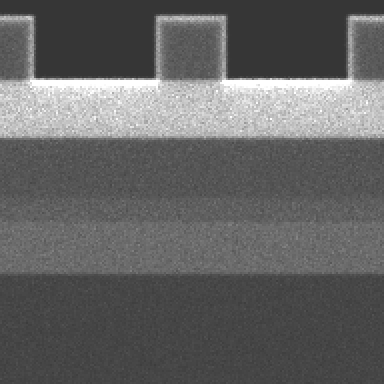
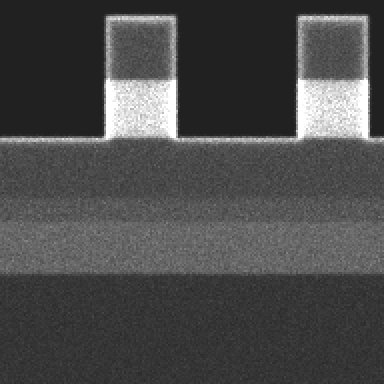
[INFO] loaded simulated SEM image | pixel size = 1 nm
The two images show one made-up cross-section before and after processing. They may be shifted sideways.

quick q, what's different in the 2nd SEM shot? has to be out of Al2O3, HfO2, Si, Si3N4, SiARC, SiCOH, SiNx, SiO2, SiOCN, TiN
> HfO2 removed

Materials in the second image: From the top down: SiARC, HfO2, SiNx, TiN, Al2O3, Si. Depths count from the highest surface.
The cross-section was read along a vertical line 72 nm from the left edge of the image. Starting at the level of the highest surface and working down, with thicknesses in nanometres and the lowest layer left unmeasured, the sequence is empty 122, SiNx 60, TiN 24, Al2O3 52, Si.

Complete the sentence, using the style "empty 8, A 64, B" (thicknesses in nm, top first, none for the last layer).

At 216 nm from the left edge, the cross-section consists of empty 122, SiNx 60, TiN 24, Al2O3 52, Si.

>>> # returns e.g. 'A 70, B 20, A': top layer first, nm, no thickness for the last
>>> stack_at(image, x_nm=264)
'empty 122, SiNx 60, TiN 24, Al2O3 52, Si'